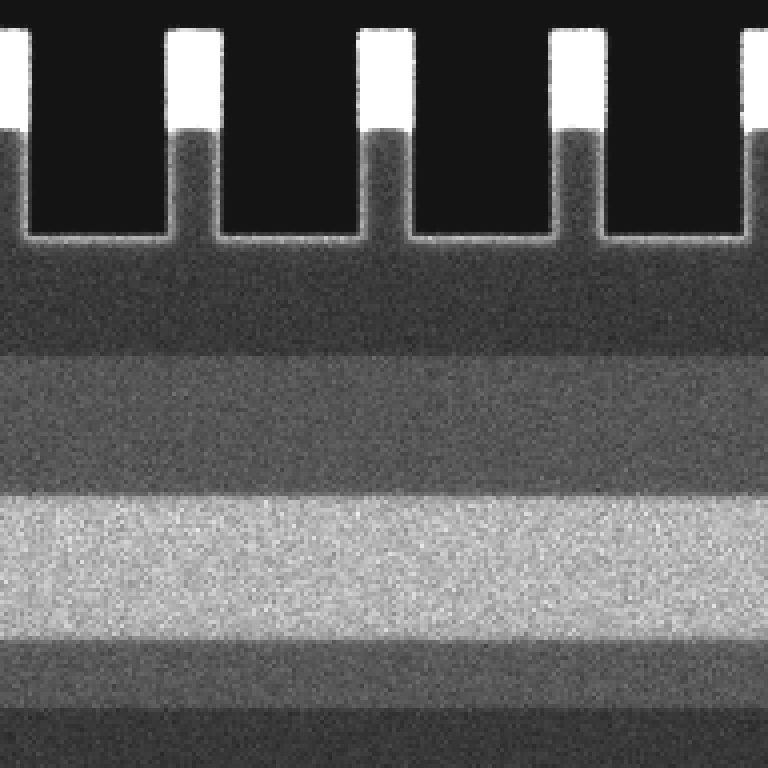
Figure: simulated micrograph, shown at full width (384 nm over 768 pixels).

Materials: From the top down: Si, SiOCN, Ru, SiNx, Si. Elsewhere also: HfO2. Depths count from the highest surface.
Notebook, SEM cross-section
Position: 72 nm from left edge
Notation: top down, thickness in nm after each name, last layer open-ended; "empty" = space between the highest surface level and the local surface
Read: empty 102, Si 60, SiOCN 70, Ru 72, SiNx 34, Si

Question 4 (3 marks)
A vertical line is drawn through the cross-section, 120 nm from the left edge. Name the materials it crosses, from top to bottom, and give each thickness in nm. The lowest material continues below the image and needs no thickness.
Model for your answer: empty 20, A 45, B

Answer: empty 102, Si 60, SiOCN 70, Ru 72, SiNx 34, Si